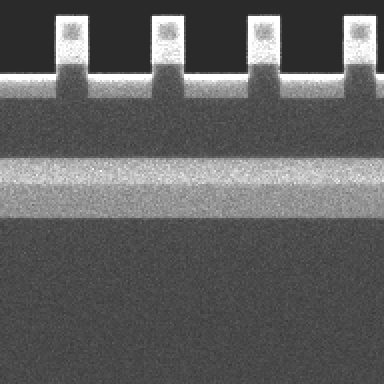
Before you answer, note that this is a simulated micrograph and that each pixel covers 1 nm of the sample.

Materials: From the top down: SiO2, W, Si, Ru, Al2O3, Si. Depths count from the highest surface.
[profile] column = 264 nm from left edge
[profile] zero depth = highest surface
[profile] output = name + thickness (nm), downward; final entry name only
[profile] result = SiO2 24, W 24, Si 94, Ru 26, Al2O3 34, Si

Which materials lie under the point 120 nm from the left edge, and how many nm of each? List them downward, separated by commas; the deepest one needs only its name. empty 58, SiO2 24, Si 60, Ru 26, Al2O3 34, Si